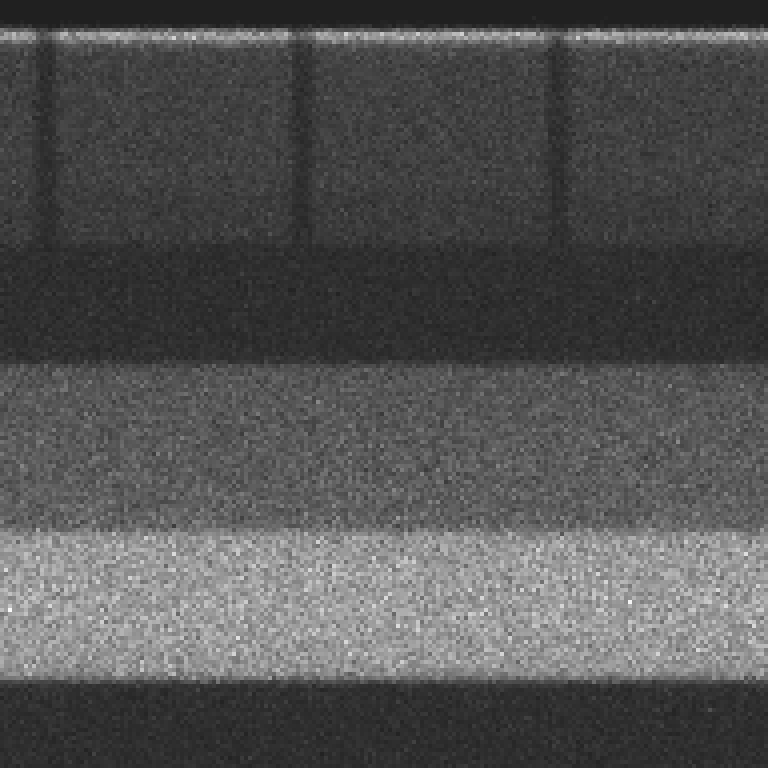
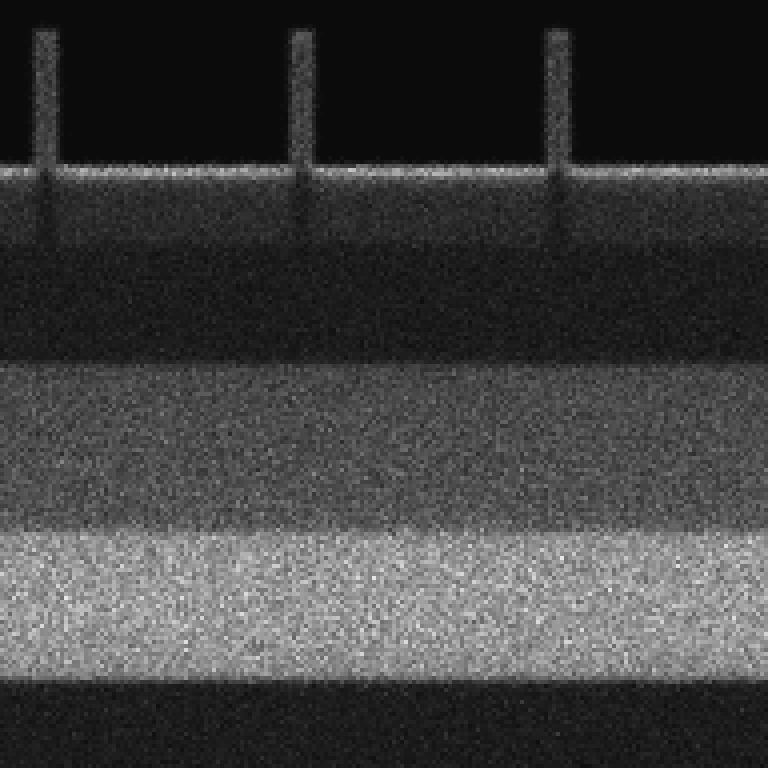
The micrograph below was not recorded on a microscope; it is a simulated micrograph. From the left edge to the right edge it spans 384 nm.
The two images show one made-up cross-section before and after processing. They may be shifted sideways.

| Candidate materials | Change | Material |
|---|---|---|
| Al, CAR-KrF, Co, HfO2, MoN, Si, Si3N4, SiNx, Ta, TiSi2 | removed | Si3N4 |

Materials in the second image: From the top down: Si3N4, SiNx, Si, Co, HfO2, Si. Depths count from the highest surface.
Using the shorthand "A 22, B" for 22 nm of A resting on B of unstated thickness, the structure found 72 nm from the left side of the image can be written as empty 68, Si3N4 12, SiNx 26, Si 60, Co 84, HfO2 74, Si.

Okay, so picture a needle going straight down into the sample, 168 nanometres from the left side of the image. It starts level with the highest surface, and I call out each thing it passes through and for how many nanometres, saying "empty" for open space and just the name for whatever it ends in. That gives empty 68, Si3N4 12, SiNx 26, Si 60, Co 84, HfO2 74, Si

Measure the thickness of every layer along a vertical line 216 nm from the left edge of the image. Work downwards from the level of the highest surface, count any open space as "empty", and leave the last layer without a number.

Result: empty 68, Si3N4 12, SiNx 26, Si 60, Co 84, HfO2 74, Si